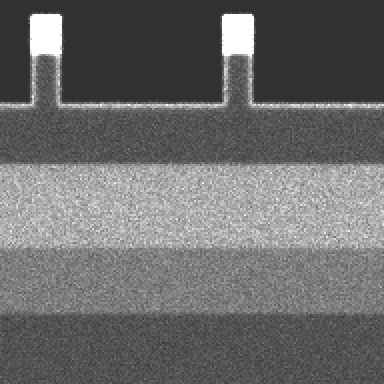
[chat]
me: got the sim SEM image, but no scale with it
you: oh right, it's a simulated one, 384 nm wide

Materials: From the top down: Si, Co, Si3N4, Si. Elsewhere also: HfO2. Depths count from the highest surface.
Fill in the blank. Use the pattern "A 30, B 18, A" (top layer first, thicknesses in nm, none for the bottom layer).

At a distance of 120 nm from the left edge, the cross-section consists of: empty 88, Si 60, Co 84, Si3N4 66, Si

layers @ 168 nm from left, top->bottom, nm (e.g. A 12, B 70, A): empty 88, Si 60, Co 84, Si3N4 66, Si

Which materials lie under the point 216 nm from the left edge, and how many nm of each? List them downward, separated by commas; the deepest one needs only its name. empty 88, Si 60, Co 84, Si3N4 66, Si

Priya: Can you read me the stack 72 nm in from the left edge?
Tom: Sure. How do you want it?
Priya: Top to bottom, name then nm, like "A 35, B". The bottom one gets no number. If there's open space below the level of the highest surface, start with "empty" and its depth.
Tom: empty 88, Si 60, Co 84, Si3N4 66, Si